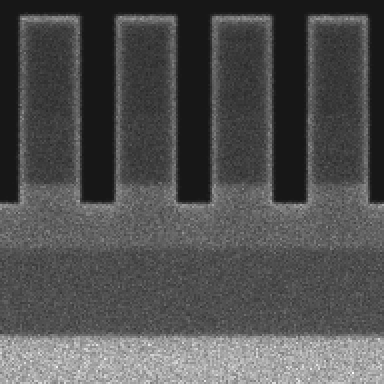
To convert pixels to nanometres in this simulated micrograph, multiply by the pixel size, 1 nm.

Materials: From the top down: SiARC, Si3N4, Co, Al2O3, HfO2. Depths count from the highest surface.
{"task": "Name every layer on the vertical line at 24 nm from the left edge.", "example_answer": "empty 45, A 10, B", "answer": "SiARC 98, Si3N4 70, Co 64, Al2O3 88, HfO2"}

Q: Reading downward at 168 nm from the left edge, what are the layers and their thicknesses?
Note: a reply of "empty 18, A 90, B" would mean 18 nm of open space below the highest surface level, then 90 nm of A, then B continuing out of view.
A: SiARC 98, Si3N4 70, Co 64, Al2O3 88, HfO2